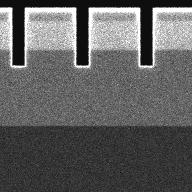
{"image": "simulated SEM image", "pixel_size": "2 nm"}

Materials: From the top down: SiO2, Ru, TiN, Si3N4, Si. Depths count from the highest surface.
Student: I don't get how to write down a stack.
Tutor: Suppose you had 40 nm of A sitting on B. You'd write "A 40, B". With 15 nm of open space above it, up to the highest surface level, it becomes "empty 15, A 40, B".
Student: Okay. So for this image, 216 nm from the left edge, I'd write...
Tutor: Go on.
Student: SiO2 26, Ru 58, TiN 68, Si3N4 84, Si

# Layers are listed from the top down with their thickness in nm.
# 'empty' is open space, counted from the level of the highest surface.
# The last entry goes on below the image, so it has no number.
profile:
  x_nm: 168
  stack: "empty 116, TiN 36, Si3N4 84, Si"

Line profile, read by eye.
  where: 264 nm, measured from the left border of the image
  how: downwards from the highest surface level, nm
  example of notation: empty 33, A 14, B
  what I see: SiO2 26, Ru 58, TiN 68, Si3N4 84, Si